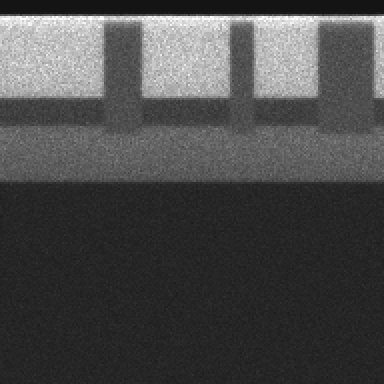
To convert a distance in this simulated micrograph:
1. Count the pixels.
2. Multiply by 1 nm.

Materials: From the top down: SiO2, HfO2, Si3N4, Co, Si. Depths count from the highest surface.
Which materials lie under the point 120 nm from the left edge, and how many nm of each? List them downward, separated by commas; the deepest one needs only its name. SiO2 118, Co 48, Si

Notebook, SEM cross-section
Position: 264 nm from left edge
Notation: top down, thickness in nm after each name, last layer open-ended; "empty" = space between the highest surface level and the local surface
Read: HfO2 82, Si3N4 28, Co 56, Si